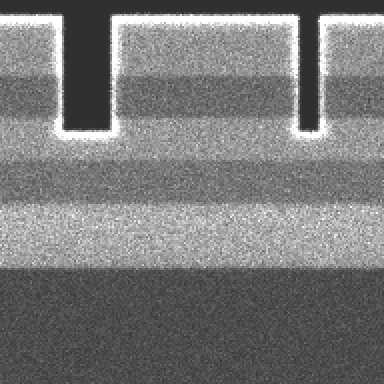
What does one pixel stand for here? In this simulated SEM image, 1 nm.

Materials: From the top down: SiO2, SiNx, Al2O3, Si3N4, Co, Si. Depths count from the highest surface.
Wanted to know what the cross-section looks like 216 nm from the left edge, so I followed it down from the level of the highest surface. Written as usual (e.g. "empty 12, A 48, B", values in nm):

SiO2 60, SiNx 42, Al2O3 42, Si3N4 44, Co 64, Si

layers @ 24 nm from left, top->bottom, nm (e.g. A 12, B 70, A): SiO2 60, SiNx 42, Al2O3 42, Si3N4 44, Co 64, Si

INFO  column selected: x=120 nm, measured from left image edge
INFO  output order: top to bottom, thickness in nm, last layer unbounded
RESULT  SiO2 60, SiNx 42, Al2O3 42, Si3N4 44, Co 64, Si